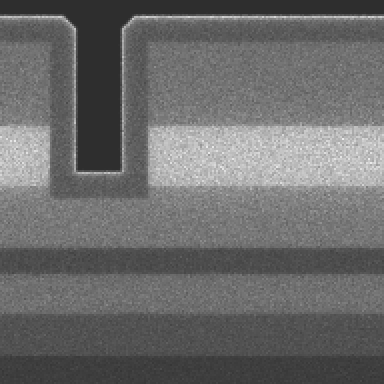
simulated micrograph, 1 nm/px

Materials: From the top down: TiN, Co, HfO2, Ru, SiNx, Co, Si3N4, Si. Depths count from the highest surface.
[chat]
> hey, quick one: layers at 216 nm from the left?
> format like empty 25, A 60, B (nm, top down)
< TiN 26, Co 84, HfO2 60, Ru 62, SiNx 26, Co 40, Si3N4 42, Si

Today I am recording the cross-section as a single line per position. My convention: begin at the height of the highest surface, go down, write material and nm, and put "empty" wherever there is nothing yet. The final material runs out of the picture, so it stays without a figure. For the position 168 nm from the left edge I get TiN 26, Co 84, HfO2 60, Ru 62, SiNx 26, Co 40, Si3N4 42, Si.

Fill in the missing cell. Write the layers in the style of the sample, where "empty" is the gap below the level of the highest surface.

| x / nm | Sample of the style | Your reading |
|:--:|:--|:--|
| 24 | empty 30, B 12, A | TiN 26, Co 84, HfO2 60, Ru 62, SiNx 26, Co 40, Si3N4 42, Si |